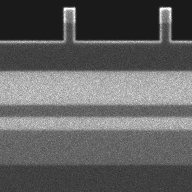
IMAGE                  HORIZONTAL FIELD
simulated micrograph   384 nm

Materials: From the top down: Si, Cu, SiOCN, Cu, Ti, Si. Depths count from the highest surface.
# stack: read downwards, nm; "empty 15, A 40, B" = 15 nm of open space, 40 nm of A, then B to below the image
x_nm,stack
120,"empty 66, Si 60, Cu 68, SiOCN 24, Cu 26, Ti 70, Si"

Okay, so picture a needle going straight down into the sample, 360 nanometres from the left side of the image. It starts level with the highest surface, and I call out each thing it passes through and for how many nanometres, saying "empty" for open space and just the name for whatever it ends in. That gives empty 66, Si 60, Cu 68, SiOCN 24, Cu 26, Ti 70, Si